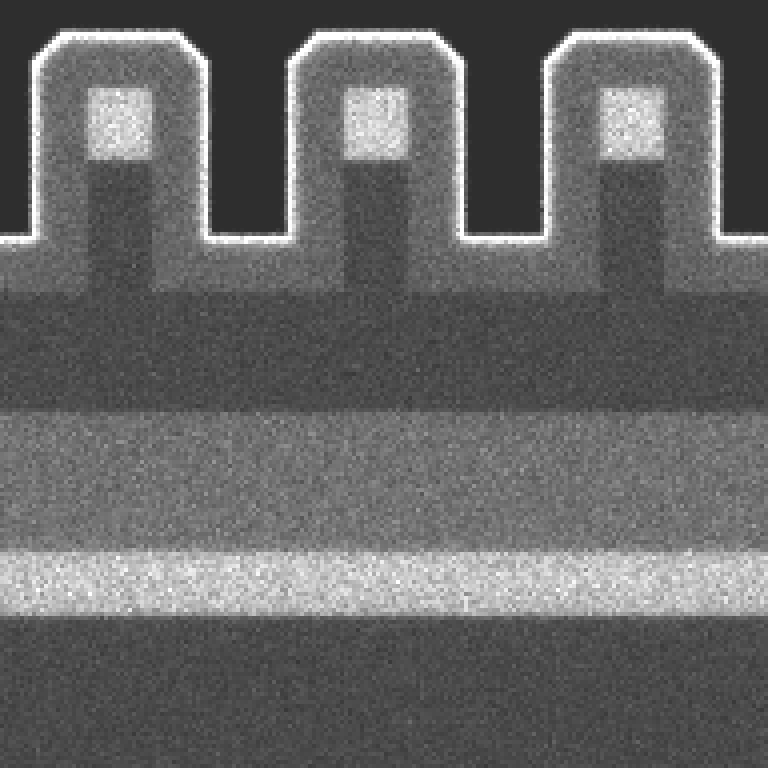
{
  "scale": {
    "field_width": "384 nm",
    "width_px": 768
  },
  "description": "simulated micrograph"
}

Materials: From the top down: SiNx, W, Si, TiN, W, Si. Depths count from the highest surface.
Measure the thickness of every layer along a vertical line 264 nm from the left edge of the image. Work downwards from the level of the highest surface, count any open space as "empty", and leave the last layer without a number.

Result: empty 102, SiNx 28, Si 60, TiN 70, W 32, Si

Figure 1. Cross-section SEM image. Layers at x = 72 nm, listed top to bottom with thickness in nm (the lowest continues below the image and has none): SiNx 28, W 36, Si 126, TiN 70, W 32, Si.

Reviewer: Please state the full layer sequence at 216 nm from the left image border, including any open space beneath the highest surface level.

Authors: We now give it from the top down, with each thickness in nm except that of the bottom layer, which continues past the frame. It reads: SiNx 130, Si 60, TiN 70, W 32, Si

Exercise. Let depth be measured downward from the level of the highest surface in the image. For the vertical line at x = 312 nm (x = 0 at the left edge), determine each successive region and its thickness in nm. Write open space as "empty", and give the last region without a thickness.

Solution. SiNx 28, W 36, Si 126, TiN 70, W 32, Si